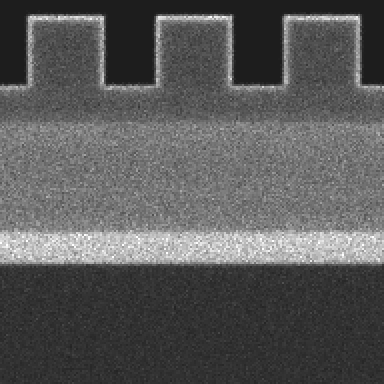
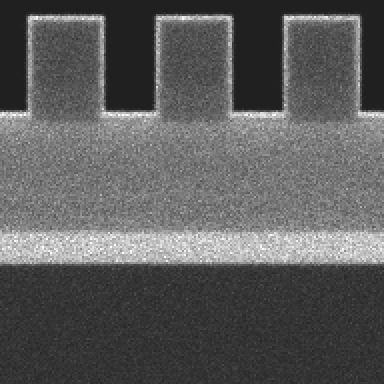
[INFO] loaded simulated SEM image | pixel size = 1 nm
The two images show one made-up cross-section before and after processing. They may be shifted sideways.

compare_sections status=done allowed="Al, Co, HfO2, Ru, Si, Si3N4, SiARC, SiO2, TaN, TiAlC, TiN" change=removed material="TiN"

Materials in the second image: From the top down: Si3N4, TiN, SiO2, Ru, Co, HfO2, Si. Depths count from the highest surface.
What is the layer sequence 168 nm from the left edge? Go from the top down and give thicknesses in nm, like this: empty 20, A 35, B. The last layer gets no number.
Si3N4 70, TiN 26, SiO2 10, Ru 78, Co 32, HfO2 32, Si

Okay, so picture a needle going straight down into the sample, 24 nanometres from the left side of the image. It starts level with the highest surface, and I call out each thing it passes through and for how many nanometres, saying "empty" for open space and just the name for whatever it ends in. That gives empty 96, SiO2 10, Ru 78, Co 32, HfO2 32, Si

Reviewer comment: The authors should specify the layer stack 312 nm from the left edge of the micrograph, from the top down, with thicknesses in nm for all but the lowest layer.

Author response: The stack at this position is Si3N4 70, TiN 26, SiO2 10, Ru 78, Co 32, HfO2 32, Si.